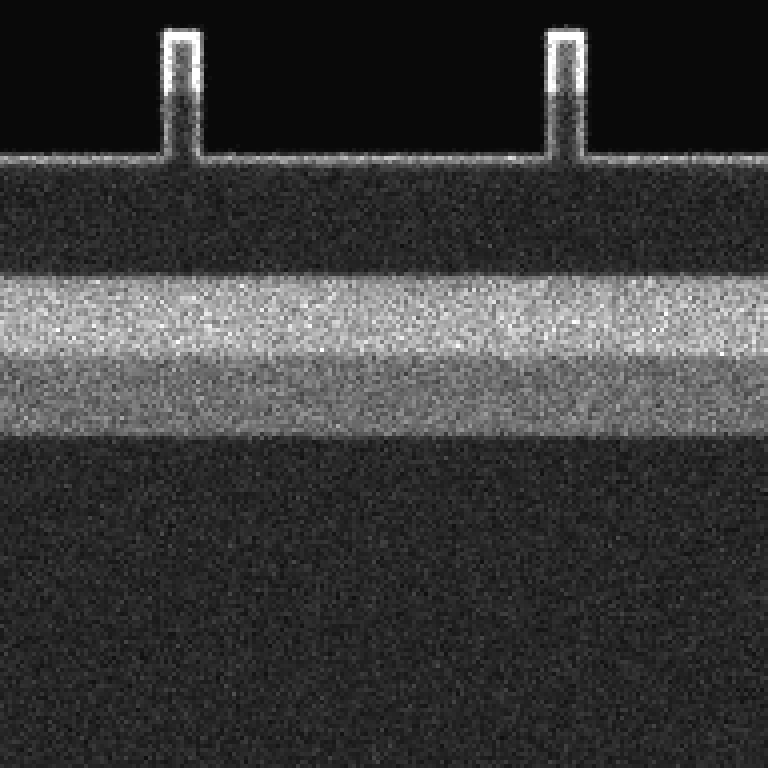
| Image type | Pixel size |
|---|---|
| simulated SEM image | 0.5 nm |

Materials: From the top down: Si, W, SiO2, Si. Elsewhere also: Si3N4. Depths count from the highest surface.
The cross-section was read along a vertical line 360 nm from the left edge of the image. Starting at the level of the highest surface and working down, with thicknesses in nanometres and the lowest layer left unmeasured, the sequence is empty 62, Si 60, W 40, SiO2 40, Si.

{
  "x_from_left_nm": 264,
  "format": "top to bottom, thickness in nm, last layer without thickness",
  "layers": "empty 62, Si 60, W 40, SiO2 40, Si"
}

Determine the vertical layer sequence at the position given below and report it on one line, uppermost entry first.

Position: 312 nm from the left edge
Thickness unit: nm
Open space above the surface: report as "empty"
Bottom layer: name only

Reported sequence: empty 62, Si 60, W 40, SiO2 40, Si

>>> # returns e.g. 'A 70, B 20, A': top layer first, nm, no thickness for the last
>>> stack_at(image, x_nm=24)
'empty 62, Si 60, W 40, SiO2 40, Si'